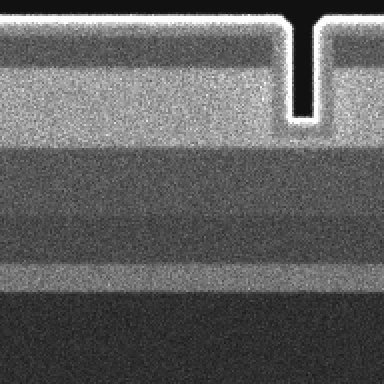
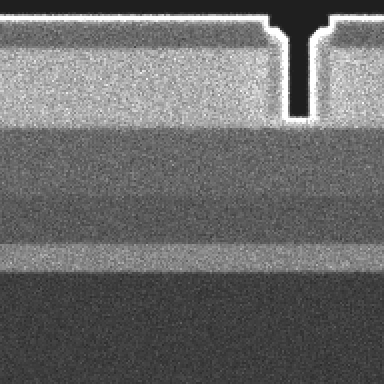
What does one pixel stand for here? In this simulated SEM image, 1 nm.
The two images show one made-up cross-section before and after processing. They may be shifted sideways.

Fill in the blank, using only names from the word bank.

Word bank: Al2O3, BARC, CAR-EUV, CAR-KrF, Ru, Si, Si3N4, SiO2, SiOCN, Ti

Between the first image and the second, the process removed Al2O3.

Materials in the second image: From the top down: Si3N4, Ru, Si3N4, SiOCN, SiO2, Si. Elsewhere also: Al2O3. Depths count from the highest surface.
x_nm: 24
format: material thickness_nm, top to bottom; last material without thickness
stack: Si3N4 32, Ru 80, Si3N4 68, SiOCN 48, SiO2 28, Si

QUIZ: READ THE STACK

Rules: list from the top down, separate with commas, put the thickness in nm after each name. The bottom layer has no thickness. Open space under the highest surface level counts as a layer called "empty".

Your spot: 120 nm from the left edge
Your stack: Si3N4 32, Ru 80, Si3N4 68, SiOCN 48, SiO2 28, Si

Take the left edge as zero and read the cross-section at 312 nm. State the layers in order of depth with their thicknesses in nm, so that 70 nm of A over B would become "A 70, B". empty 20, Al2O3 82, Ru 10, Si3N4 68, SiOCN 48, SiO2 28, Si